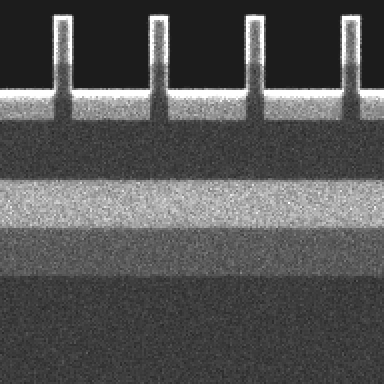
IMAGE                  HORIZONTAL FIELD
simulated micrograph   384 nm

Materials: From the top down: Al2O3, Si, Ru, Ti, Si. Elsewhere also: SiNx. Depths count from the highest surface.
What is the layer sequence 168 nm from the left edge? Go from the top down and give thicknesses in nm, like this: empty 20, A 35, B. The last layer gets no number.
empty 74, Al2O3 30, Si 60, Ru 48, Ti 48, Si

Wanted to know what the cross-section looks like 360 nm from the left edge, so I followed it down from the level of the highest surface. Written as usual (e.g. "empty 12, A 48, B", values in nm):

empty 74, Al2O3 30, Si 60, Ru 48, Ti 48, Si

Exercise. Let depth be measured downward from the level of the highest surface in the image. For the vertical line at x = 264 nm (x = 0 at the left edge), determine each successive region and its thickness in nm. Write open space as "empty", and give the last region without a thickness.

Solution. empty 74, Al2O3 30, Si 60, Ru 48, Ti 48, Si